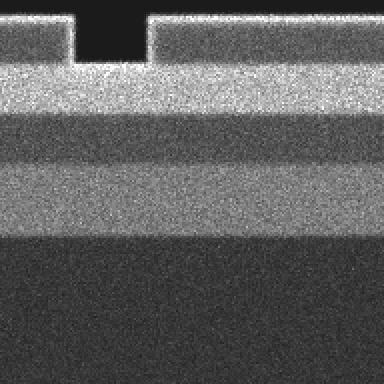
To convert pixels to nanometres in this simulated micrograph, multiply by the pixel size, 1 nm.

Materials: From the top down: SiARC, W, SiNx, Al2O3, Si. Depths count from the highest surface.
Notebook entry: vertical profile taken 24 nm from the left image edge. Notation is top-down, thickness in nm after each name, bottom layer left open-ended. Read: SiARC 48, W 50, SiNx 50, Al2O3 72, Si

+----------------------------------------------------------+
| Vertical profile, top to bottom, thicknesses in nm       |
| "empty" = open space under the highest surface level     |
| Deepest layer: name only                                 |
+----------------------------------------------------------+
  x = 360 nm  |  SiARC 48, W 50, SiNx 50, Al2O3 72, Si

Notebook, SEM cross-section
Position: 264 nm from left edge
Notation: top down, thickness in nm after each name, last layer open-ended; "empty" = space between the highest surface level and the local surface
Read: SiARC 48, W 50, SiNx 50, Al2O3 72, Si